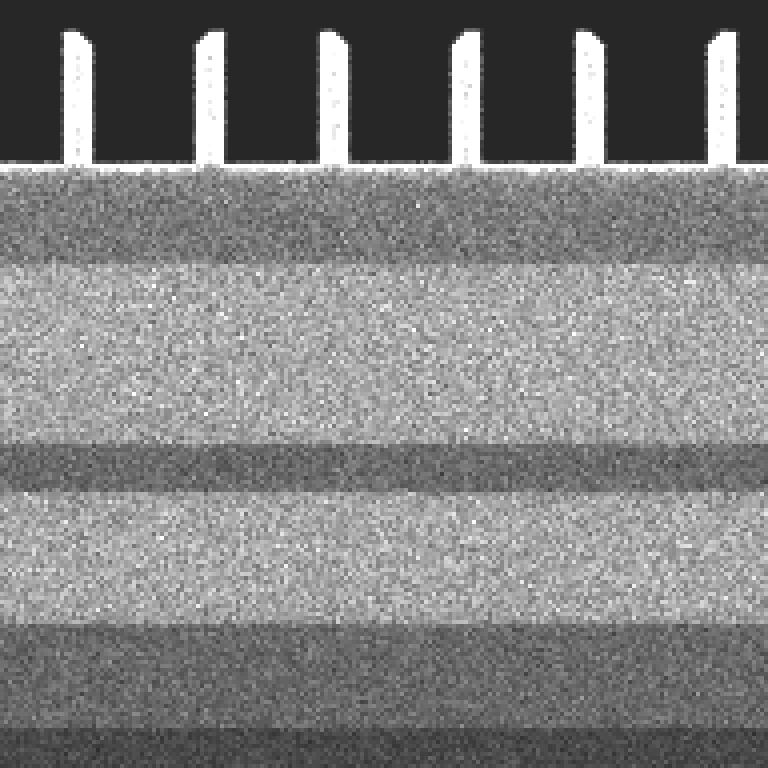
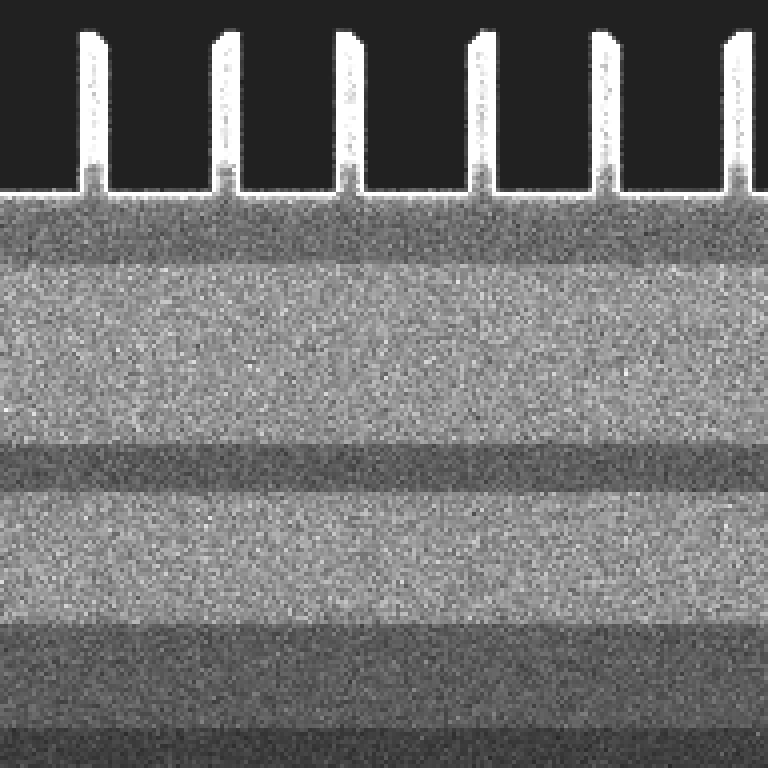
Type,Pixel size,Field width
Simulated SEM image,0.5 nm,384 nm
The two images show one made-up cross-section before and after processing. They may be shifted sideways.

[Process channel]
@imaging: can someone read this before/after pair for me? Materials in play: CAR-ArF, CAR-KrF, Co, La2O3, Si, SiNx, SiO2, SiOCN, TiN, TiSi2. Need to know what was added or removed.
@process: TiN removed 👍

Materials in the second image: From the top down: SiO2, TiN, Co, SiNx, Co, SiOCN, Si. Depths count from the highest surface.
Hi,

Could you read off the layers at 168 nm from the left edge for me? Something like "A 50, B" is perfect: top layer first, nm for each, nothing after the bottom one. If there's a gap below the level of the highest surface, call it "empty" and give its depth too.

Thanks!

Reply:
SiO2 66, TiN 50, Co 90, SiNx 24, Co 66, SiOCN 52, Si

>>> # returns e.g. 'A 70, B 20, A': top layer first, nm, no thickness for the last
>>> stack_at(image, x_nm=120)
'empty 80, TiN 36, Co 90, SiNx 24, Co 66, SiOCN 52, Si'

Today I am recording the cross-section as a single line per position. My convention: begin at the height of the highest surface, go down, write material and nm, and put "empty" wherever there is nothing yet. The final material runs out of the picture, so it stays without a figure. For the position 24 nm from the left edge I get empty 80, TiN 36, Co 90, SiNx 24, Co 66, SiOCN 52, Si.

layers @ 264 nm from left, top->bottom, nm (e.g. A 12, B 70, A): empty 80, TiN 36, Co 90, SiNx 24, Co 66, SiOCN 52, Si